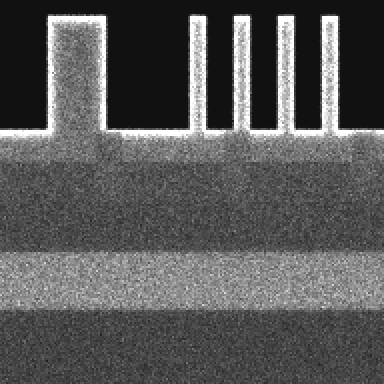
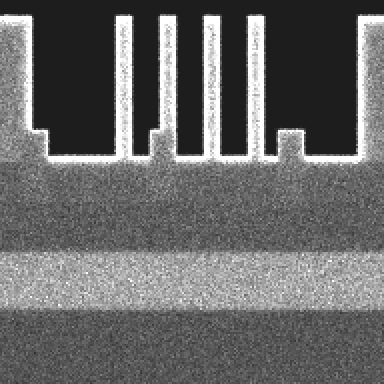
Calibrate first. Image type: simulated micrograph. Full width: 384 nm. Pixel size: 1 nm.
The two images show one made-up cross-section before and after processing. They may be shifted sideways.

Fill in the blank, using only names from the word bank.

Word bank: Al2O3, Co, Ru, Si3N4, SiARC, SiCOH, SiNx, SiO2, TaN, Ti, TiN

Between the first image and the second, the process removed Al2O3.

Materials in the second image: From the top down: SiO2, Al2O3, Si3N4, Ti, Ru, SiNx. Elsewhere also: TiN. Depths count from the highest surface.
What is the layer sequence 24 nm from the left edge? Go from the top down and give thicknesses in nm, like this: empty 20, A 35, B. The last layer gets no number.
SiO2 114, TiN 72, Ti 50, Ru 58, SiNx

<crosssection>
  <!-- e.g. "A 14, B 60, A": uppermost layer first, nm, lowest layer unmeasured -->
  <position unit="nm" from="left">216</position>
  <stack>SiO2 114, Al2O3 32, Si3N4 40, Ti 50, Ru 58, SiNx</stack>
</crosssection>